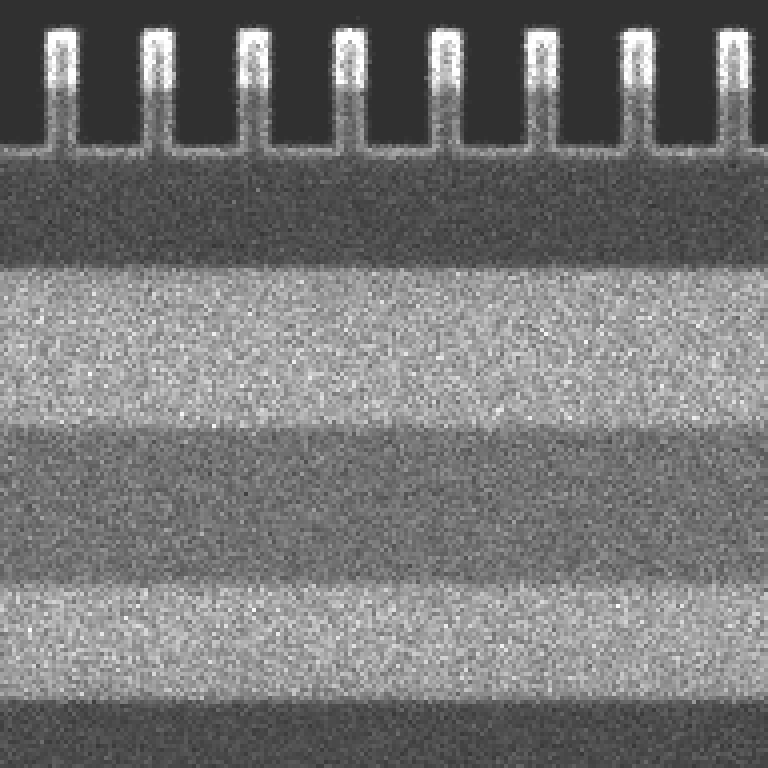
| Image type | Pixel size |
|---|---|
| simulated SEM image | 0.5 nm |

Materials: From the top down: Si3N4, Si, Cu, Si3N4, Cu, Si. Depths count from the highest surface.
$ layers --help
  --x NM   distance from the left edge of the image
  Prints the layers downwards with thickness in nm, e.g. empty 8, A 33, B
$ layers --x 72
Si3N4 28, Si 90, Cu 80, Si3N4 78, Cu 58, Si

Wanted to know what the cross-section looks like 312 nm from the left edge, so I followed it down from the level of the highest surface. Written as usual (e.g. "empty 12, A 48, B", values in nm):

Si3N4 28, Si 90, Cu 80, Si3N4 78, Cu 58, Si